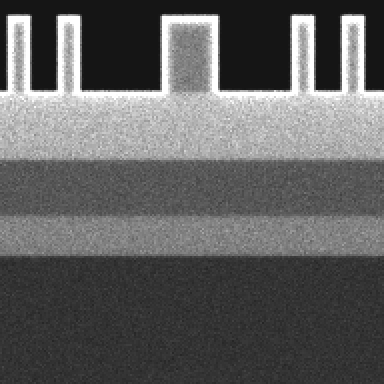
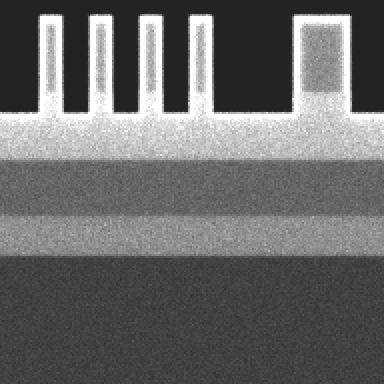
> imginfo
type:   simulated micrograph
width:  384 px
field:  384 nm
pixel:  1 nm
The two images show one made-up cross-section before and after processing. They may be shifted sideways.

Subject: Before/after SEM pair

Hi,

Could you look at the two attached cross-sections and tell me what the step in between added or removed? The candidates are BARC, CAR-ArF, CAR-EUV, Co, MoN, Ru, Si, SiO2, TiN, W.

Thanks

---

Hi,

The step removed W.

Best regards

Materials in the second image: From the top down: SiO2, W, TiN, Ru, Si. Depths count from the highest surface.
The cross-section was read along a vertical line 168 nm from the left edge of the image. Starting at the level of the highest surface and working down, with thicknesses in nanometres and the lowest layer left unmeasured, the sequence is empty 98, W 46, TiN 56, Ru 40, Si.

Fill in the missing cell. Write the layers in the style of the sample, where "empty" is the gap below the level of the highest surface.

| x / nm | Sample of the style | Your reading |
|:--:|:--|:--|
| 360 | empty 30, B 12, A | empty 98, W 46, TiN 56, Ru 40, Si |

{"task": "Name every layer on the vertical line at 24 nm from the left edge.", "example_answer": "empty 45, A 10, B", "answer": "empty 98, W 46, TiN 56, Ru 40, Si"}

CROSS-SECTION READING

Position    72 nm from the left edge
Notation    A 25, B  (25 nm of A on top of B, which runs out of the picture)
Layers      empty 98, W 46, TiN 56, Ru 40, Si